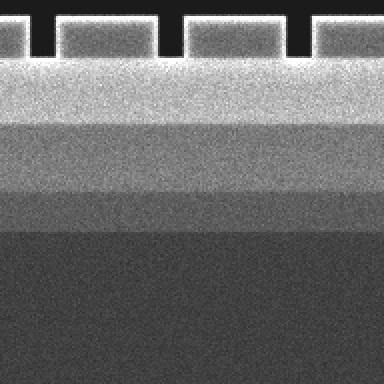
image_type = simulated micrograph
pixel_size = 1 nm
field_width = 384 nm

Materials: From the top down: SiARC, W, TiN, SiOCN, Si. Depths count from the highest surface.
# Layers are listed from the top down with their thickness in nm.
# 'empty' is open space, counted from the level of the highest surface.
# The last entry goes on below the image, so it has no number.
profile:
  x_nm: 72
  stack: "SiARC 42, W 66, TiN 68, SiOCN 40, Si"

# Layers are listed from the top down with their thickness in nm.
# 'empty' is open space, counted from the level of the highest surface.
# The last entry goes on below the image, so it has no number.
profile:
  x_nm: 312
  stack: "SiARC 42, W 66, TiN 68, SiOCN 40, Si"